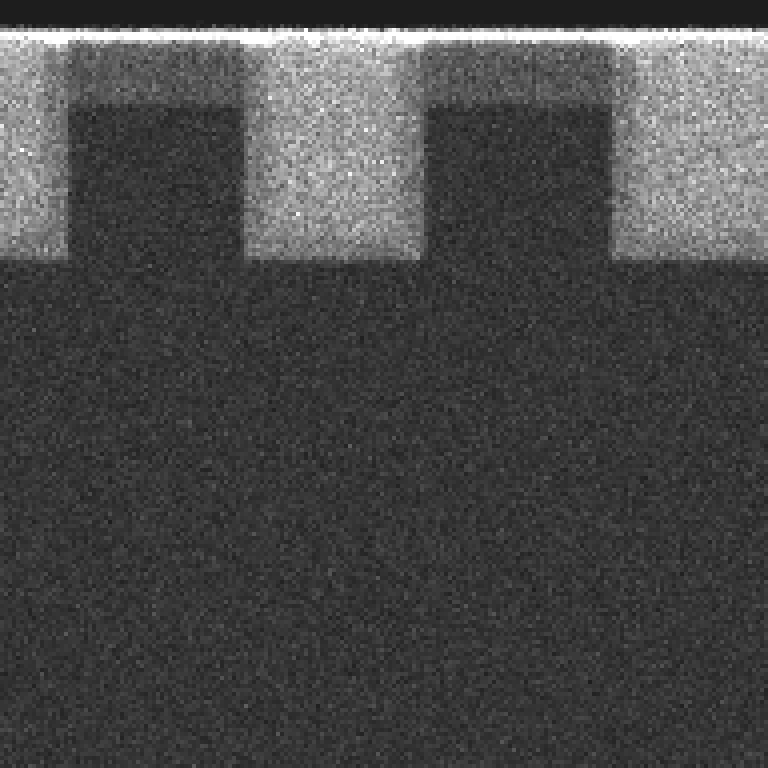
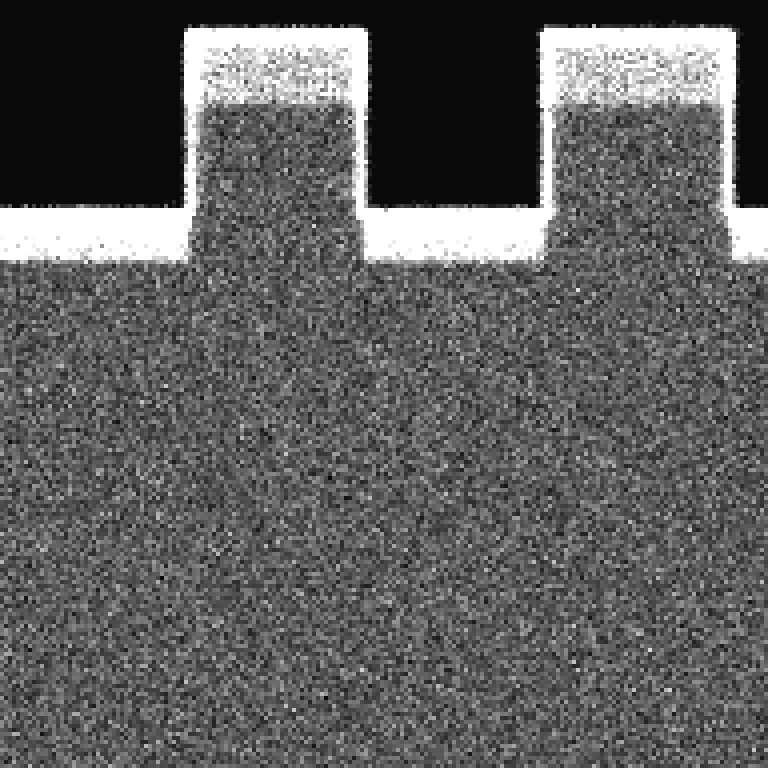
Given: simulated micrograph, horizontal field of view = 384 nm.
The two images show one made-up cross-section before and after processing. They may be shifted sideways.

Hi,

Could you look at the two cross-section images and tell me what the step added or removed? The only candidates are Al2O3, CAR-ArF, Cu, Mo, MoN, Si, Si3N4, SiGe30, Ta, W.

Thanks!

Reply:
removed Al2O3 and W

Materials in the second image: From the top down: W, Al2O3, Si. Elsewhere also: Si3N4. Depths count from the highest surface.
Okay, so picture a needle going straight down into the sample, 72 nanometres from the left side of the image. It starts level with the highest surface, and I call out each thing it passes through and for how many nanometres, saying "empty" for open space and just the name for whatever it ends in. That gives empty 90, W 12, Al2O3 12, Si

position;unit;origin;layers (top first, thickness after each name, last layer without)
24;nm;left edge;empty 90, W 12, Al2O3 12, Si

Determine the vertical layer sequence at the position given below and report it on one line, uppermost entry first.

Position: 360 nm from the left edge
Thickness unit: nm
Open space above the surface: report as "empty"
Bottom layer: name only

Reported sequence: Si3N4 36, Si